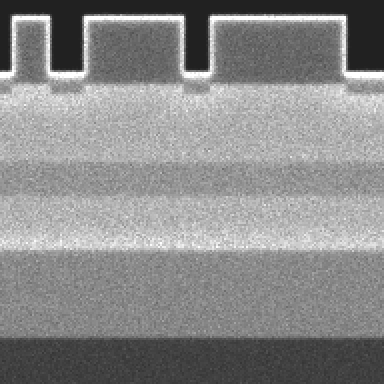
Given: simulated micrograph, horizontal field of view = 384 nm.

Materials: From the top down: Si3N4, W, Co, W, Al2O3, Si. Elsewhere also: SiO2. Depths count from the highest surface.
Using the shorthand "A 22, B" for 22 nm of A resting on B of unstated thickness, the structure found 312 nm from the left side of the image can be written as Si3N4 68, W 78, Co 34, W 54, Al2O3 88, Si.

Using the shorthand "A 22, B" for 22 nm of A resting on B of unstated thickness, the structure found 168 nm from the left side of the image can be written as Si3N4 68, W 78, Co 34, W 54, Al2O3 88, Si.